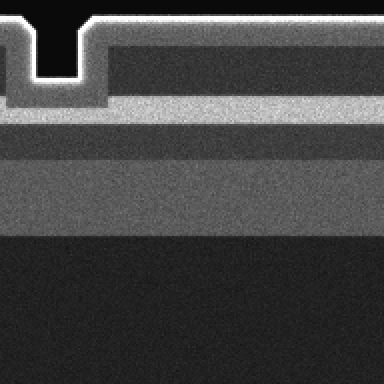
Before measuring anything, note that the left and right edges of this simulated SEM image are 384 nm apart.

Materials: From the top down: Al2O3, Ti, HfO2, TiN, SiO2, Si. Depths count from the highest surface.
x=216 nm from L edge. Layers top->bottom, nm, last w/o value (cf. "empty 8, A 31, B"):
Al2O3 30, Ti 50, HfO2 28, TiN 36, SiO2 76, Si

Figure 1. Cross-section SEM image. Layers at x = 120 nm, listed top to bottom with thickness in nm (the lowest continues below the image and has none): Al2O3 30, Ti 50, HfO2 28, TiN 36, SiO2 76, Si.